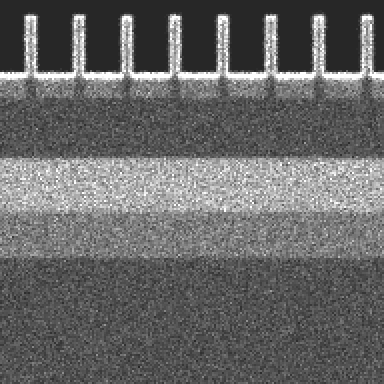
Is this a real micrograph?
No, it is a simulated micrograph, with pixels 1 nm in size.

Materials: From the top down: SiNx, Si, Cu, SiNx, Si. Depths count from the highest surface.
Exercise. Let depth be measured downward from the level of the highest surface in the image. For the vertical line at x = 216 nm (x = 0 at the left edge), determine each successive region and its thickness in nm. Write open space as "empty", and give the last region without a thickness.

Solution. empty 58, SiNx 24, Si 60, Cu 54, SiNx 46, Si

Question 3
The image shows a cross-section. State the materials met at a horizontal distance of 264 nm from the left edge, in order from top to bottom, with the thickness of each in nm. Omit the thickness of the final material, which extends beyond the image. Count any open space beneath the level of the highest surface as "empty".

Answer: empty 58, SiNx 24, Si 60, Cu 54, SiNx 46, Si